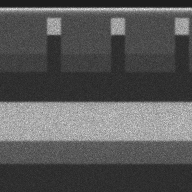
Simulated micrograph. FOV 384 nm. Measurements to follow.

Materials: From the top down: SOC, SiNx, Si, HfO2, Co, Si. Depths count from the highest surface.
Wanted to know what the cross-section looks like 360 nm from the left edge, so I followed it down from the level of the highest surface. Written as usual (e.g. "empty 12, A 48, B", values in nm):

SOC 20, HfO2 34, Si 134, HfO2 78, Co 46, Si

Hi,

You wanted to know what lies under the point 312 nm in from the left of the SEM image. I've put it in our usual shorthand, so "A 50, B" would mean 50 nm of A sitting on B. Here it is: SOC 92, SiNx 36, Si 60, HfO2 78, Co 46, Si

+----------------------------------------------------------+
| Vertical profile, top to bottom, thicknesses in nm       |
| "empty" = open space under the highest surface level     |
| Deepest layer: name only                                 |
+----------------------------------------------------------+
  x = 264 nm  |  SOC 92, SiNx 36, Si 60, HfO2 78, Co 46, Si